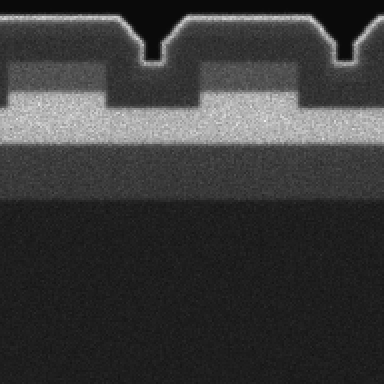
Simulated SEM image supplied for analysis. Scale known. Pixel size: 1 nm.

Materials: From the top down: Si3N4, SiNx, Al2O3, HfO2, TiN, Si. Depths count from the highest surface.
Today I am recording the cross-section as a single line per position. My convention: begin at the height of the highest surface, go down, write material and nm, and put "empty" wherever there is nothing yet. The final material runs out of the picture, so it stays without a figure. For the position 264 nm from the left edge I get Si3N4 20, SiNx 26, Al2O3 30, HfO2 52, TiN 56, Si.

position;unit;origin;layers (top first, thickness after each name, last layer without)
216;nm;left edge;Si3N4 20, SiNx 26, Al2O3 30, HfO2 52, TiN 56, Si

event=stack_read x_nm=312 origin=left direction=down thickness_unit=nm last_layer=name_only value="empty 2, Si3N4 20, SiNx 70, HfO2 36, TiN 56, Si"